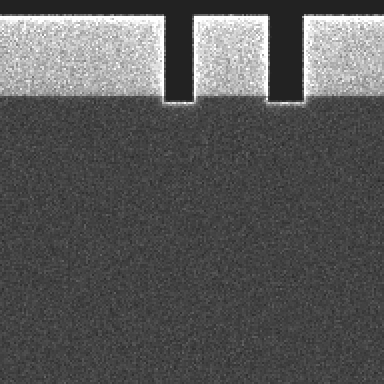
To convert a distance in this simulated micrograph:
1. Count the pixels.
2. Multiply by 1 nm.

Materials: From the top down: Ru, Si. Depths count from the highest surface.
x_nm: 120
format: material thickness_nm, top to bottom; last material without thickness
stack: Ru 80, Si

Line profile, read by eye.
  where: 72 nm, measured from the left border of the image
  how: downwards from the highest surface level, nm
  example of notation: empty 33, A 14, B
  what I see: Ru 80, Si